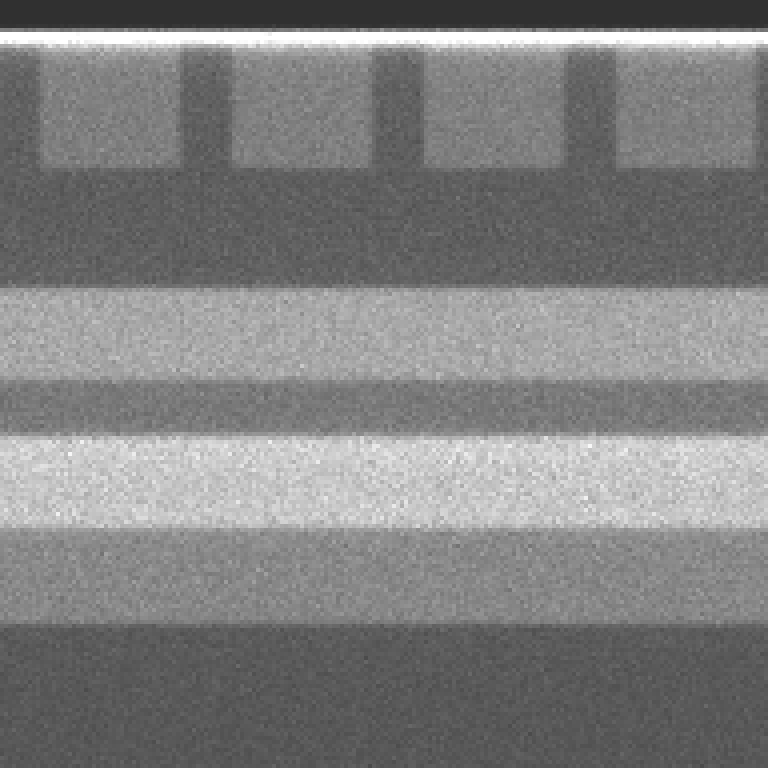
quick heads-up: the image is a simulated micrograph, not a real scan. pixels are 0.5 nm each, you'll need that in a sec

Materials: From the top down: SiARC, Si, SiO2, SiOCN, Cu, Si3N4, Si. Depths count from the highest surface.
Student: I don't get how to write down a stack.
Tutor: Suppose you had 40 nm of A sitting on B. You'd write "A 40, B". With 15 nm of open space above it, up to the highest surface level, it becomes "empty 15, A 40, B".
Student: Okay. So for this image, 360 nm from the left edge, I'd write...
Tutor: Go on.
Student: SiARC 68, Si 60, SiO2 46, SiOCN 28, Cu 46, Si3N4 48, Si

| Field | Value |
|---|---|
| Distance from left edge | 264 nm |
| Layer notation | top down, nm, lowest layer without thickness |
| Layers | SiARC 68, Si 60, SiO2 46, SiOCN 28, Cu 46, Si3N4 48, Si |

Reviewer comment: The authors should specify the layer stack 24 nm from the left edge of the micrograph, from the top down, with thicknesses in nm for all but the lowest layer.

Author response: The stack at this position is SiARC 68, Si 60, SiO2 46, SiOCN 28, Cu 46, Si3N4 48, Si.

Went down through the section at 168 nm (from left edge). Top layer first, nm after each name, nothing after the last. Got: SiARC 68, Si 60, SiO2 46, SiOCN 28, Cu 46, Si3N4 48, Si